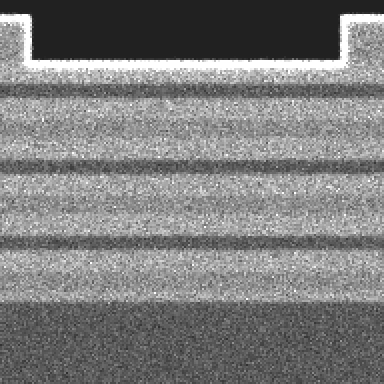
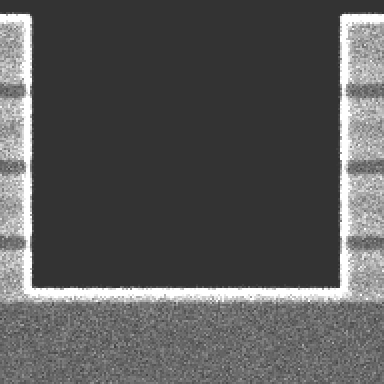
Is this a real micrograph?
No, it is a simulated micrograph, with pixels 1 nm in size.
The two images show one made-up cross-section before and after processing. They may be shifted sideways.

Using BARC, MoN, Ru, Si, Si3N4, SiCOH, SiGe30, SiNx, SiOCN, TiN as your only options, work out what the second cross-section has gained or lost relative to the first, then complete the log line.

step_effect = removed Si and Si3N4 and SiOCN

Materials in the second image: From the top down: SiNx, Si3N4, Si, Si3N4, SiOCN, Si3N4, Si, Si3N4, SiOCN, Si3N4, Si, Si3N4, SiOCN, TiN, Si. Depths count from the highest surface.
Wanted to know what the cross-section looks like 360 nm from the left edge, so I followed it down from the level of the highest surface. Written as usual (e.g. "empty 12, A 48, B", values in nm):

SiNx 46, Si3N4 22, Si 14, Si3N4 22, SiOCN 18, Si3N4 22, Si 14, Si3N4 22, SiOCN 18, Si3N4 22, Si 14, Si3N4 22, SiOCN 18, TiN 12, Si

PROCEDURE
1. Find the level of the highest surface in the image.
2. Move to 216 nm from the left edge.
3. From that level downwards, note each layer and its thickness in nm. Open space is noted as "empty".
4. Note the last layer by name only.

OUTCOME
empty 274, TiN 12, Si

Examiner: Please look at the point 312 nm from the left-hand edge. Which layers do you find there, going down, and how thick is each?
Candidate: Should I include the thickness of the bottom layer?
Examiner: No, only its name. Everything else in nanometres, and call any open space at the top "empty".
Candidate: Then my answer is empty 274, TiN 12, Si